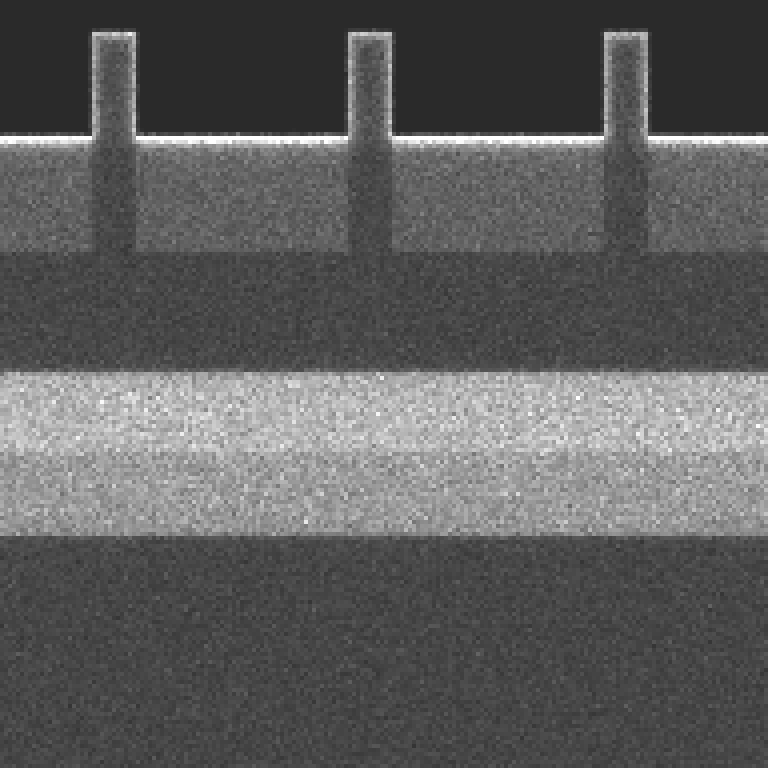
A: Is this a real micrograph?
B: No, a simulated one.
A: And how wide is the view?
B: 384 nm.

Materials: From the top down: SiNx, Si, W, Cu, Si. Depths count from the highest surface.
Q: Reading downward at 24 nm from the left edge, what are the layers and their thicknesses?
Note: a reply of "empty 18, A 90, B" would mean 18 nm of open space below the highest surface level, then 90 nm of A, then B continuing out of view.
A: empty 52, SiNx 58, Si 60, W 40, Cu 42, Si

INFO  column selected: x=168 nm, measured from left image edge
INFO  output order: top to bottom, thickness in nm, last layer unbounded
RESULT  empty 52, SiNx 58, Si 60, W 40, Cu 42, Si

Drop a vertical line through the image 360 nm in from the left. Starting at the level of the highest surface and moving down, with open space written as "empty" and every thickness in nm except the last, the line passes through empty 52, SiNx 58, Si 60, W 40, Cu 42, Si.